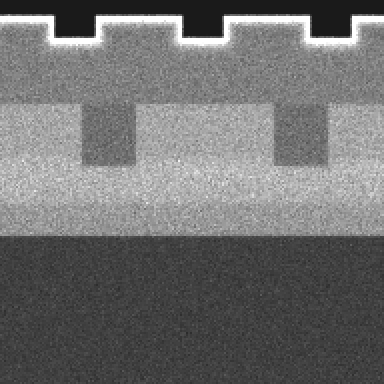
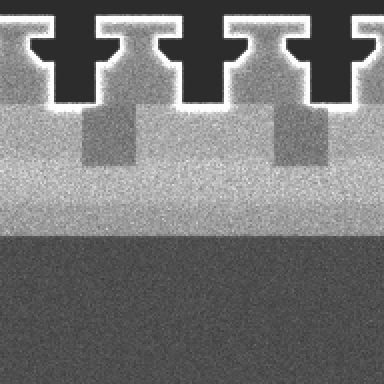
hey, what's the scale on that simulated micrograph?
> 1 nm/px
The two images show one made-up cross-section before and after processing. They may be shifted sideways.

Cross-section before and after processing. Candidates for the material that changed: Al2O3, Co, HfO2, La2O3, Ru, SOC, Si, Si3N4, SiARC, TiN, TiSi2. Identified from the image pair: SOC (removed).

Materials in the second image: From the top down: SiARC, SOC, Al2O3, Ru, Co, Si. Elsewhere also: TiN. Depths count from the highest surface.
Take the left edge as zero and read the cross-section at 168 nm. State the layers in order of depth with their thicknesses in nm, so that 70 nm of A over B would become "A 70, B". SiARC 22, empty 22, SOC 44, Al2O3 54, Ru 46, Co 32, Si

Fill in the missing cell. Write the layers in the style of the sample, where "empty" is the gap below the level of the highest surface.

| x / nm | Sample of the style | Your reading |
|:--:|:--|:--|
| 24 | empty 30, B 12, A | SiARC 22, SOC 66, Al2O3 54, Ru 46, Co 32, Si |